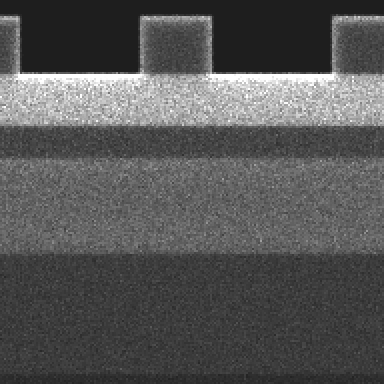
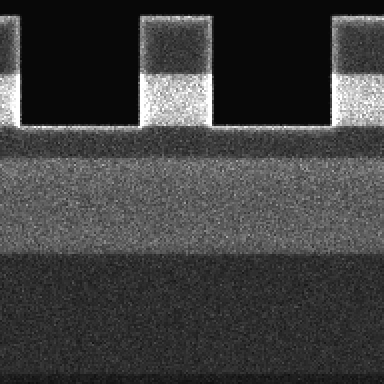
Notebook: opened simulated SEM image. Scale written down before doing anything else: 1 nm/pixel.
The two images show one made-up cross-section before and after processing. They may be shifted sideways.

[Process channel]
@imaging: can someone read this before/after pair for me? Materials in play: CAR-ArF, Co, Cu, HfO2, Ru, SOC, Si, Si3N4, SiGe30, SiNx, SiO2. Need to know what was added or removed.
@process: HfO2 removed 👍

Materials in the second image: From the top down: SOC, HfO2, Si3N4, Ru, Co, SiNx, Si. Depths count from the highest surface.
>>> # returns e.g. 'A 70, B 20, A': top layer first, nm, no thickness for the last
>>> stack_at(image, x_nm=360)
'SOC 58, HfO2 52, Si3N4 32, Ru 86, Co 10, SiNx 120, Si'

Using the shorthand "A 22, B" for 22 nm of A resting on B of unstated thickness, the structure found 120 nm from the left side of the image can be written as empty 110, Si3N4 32, Ru 86, Co 10, SiNx 120, Si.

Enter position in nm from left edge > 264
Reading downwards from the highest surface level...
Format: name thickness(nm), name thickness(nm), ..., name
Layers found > empty 110, Si3N4 32, Ru 86, Co 10, SiNx 120, Si